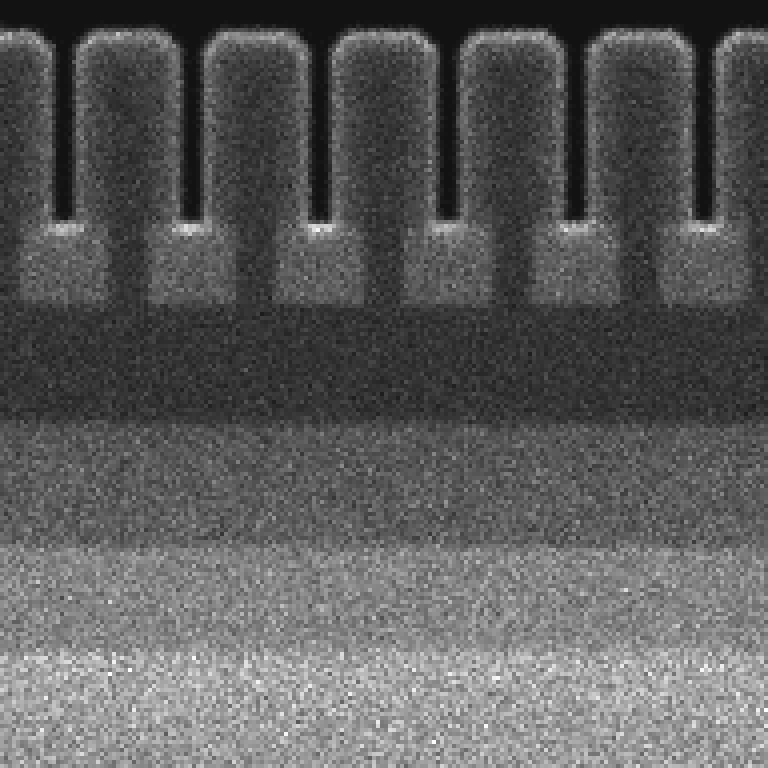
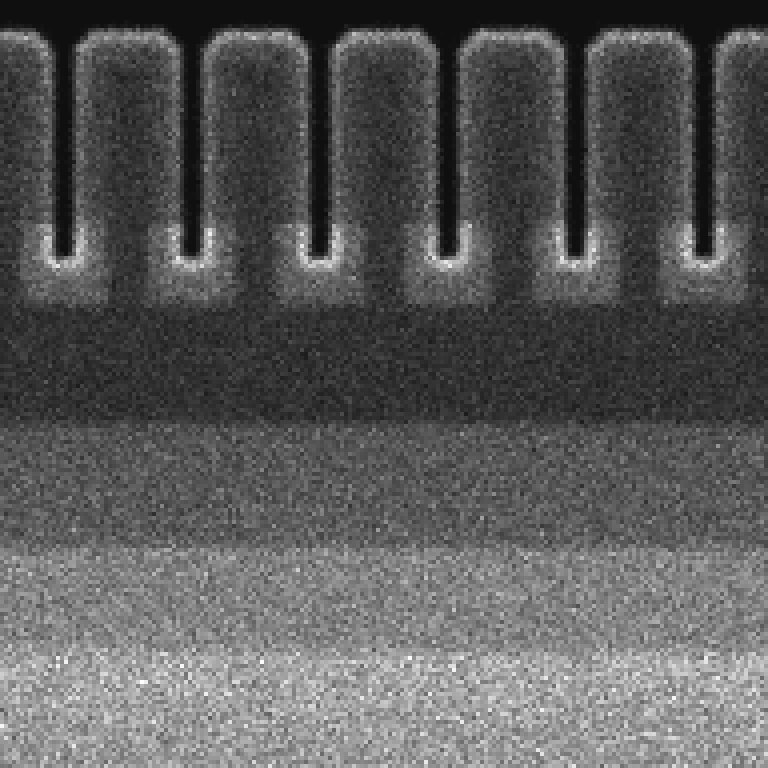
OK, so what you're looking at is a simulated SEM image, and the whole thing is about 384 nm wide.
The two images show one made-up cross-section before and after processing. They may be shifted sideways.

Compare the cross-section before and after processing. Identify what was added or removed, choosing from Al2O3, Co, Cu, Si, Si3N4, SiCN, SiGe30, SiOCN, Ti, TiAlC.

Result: Si3N4 removed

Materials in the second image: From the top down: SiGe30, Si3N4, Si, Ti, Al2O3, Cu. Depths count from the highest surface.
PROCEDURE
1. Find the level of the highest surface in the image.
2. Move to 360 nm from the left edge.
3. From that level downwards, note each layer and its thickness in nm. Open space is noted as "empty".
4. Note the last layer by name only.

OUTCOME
empty 6, SiGe30 90, Si3N4 40, Si 60, Ti 62, Al2O3 52, Cu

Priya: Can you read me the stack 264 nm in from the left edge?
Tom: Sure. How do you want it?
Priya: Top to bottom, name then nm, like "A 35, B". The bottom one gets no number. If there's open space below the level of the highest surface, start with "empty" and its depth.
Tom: SiGe30 16, Si 180, Ti 62, Al2O3 52, Cu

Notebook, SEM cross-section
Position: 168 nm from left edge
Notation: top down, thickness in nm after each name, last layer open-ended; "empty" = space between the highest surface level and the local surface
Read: empty 6, SiGe30 90, Si3N4 40, Si 60, Ti 62, Al2O3 52, Cu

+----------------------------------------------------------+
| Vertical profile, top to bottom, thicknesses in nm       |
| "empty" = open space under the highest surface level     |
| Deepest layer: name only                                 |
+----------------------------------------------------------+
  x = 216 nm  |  empty 8, SiGe30 88, Si3N4 40, Si 60, Ti 62, Al2O3 52, Cu